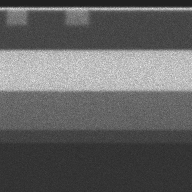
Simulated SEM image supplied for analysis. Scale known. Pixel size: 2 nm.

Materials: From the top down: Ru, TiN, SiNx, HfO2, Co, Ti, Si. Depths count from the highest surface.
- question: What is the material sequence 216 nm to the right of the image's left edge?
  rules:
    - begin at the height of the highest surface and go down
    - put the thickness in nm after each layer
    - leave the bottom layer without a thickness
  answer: SiNx 84, HfO2 82, Co 78, Ti 26, Si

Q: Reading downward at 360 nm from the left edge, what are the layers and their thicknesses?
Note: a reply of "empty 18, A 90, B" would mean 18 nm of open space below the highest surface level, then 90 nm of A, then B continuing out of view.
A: SiNx 84, HfO2 82, Co 78, Ti 26, Si